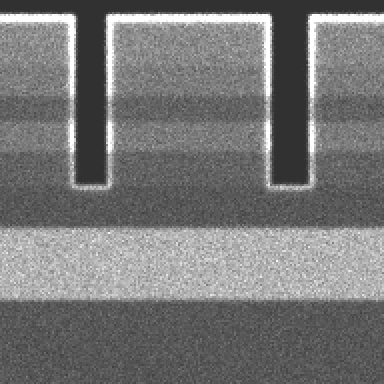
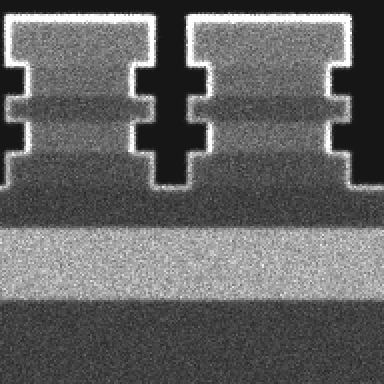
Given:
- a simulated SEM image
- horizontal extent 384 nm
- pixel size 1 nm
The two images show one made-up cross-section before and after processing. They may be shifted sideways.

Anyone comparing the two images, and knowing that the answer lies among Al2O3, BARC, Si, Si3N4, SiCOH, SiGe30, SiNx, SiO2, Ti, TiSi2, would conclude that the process removed SiNx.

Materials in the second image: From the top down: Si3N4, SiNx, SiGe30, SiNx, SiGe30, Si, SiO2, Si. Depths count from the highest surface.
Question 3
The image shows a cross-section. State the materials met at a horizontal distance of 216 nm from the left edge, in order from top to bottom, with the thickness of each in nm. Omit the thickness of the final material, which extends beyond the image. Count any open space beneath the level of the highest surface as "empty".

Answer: Si3N4 50, SiNx 30, SiGe30 26, SiNx 30, SiGe30 34, Si 42, SiO2 72, Si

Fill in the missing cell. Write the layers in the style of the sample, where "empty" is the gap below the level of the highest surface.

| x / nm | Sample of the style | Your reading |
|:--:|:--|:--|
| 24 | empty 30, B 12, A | Si3N4 50, empty 30, SiGe30 26, empty 30, SiGe30 34, Si 42, SiO2 72, Si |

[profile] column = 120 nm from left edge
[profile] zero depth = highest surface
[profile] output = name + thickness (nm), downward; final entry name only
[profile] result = Si3N4 50, SiNx 30, SiGe30 26, SiNx 30, SiGe30 34, Si 42, SiO2 72, Si